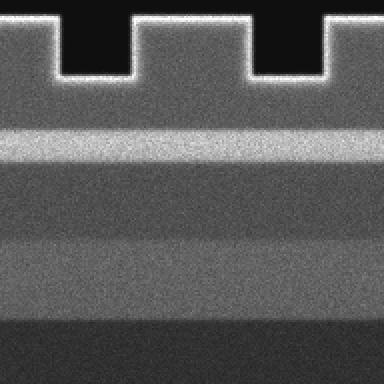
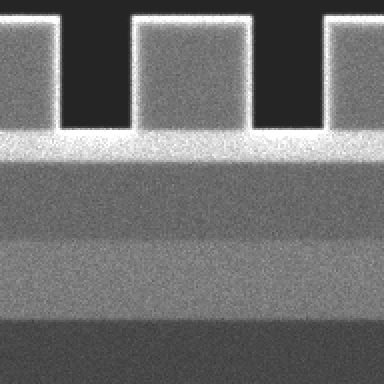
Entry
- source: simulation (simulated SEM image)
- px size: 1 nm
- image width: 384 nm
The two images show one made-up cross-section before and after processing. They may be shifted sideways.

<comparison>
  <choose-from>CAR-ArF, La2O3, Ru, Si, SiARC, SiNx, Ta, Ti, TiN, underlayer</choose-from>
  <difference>underlayer removed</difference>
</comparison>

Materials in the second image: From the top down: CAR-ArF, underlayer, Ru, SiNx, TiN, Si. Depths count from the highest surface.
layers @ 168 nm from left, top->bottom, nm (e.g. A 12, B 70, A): CAR-ArF 60, underlayer 54, Ru 32, SiNx 78, TiN 80, Si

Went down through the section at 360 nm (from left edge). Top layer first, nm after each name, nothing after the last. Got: CAR-ArF 60, underlayer 54, Ru 32, SiNx 78, TiN 80, Si